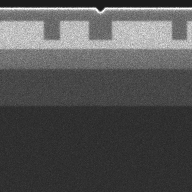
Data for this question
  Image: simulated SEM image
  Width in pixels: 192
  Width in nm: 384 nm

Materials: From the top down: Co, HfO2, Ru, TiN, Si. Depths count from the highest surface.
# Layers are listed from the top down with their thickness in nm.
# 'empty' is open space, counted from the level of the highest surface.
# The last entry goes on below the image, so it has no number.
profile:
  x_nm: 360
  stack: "Co 64, HfO2 18, Ru 40, TiN 74, Si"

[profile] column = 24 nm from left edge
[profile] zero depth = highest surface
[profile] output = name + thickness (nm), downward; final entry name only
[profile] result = Co 26, HfO2 56, Ru 40, TiN 74, Si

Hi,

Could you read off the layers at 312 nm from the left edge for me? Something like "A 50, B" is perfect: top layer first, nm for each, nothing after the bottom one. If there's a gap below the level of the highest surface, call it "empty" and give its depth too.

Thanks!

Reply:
Co 26, HfO2 56, Ru 40, TiN 74, Si